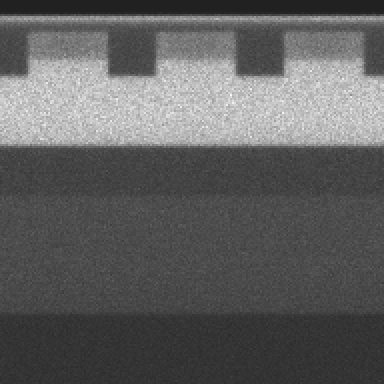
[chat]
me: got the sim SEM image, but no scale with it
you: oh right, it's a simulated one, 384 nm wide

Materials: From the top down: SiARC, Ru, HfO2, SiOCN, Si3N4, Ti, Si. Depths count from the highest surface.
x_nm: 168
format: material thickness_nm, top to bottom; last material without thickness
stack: SiARC 16, Ru 28, HfO2 86, SiOCN 50, Si3N4 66, Ti 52, Si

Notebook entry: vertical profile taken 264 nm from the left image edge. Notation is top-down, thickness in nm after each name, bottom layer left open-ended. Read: SiARC 60, HfO2 70, SiOCN 50, Si3N4 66, Ti 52, Si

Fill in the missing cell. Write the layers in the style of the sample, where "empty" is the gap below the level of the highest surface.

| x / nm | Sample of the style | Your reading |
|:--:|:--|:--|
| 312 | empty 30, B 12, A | SiARC 16, Ru 28, HfO2 86, SiOCN 50, Si3N4 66, Ti 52, Si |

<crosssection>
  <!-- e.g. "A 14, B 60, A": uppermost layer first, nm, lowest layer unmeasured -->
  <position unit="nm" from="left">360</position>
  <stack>SiARC 16, Ru 28, HfO2 86, SiOCN 50, Si3N4 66, Ti 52, Si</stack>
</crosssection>